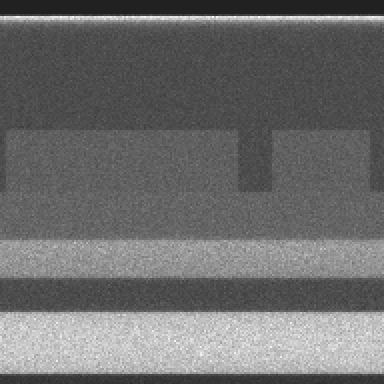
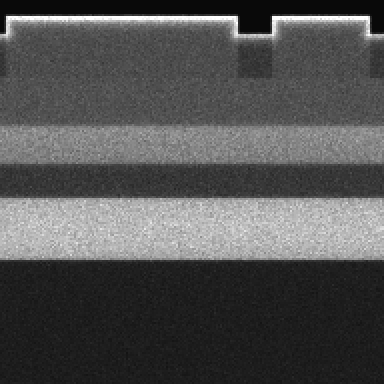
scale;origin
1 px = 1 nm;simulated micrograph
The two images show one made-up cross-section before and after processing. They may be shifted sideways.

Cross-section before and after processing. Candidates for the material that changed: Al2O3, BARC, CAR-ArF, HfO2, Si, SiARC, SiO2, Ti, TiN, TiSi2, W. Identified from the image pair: SiARC (removed).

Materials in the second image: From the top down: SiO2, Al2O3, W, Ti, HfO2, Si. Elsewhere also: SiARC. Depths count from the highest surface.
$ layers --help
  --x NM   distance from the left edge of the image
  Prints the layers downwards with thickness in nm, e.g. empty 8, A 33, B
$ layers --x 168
SiO2 62, Al2O3 48, W 38, Ti 34, HfO2 62, Si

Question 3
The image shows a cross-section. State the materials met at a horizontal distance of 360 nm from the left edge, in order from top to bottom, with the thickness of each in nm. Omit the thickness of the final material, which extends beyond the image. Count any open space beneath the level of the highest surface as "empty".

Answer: SiO2 62, Al2O3 48, W 38, Ti 34, HfO2 62, Si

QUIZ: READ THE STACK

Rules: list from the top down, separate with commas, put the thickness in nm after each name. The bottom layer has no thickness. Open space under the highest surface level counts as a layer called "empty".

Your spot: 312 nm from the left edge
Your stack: SiO2 62, Al2O3 48, W 38, Ti 34, HfO2 62, Si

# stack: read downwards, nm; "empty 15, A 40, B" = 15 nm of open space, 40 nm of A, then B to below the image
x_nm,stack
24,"SiO2 62, Al2O3 48, W 38, Ti 34, HfO2 62, Si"